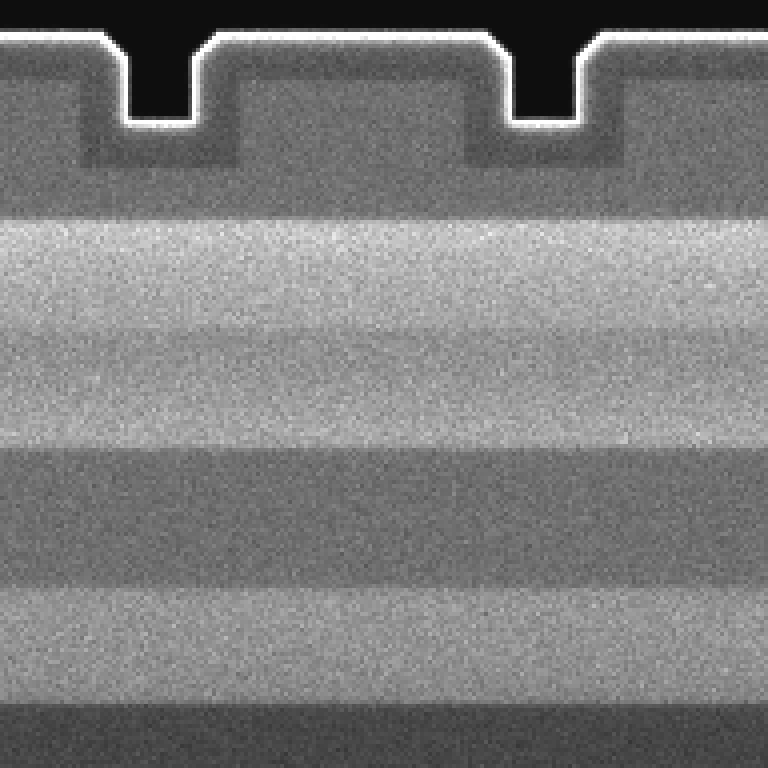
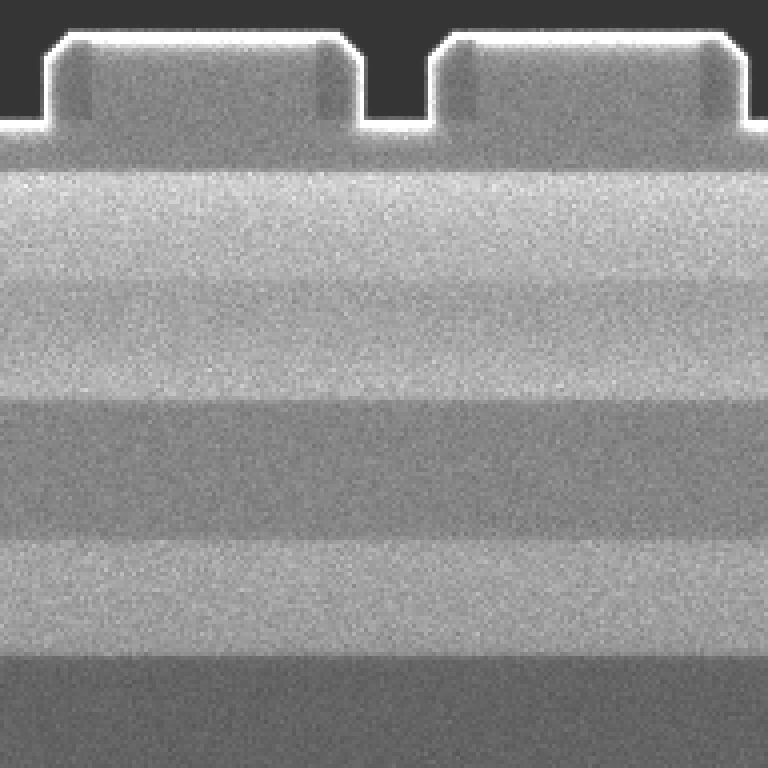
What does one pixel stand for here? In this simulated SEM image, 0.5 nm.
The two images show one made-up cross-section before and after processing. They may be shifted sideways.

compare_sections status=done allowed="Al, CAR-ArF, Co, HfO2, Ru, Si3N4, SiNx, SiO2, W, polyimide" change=removed material="Si3N4"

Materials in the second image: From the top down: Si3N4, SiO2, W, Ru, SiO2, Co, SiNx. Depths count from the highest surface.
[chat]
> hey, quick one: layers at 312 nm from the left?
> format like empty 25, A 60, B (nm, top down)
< SiO2 70, W 54, Ru 60, SiO2 70, Co 58, SiNx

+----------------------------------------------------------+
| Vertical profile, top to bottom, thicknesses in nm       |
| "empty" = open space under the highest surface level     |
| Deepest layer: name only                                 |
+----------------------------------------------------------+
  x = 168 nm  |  Si3N4 44, SiO2 26, W 54, Ru 60, SiO2 70, Co 58, SiNx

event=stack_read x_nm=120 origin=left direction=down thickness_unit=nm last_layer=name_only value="SiO2 70, W 54, Ru 60, SiO2 70, Co 58, SiNx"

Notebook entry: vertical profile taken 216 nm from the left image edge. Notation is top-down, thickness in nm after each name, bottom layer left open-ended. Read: empty 10, Si3N4 34, SiO2 26, W 54, Ru 60, SiO2 70, Co 58, SiNx